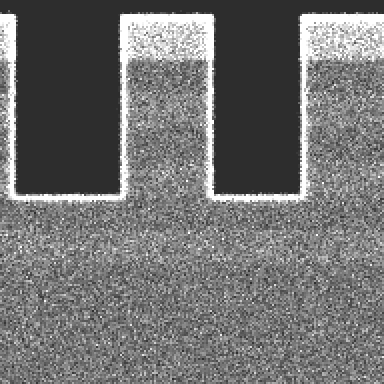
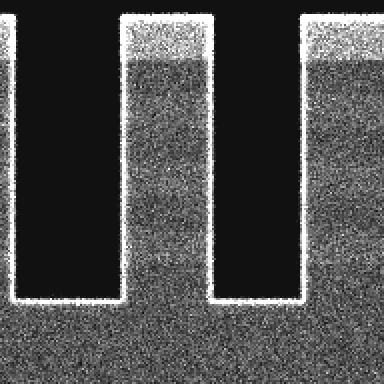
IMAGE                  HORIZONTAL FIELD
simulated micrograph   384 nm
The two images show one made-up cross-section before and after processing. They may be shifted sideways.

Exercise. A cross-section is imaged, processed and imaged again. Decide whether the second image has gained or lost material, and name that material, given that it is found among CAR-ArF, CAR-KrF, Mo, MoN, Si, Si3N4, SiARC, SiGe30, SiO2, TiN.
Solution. removed: Si and SiGe30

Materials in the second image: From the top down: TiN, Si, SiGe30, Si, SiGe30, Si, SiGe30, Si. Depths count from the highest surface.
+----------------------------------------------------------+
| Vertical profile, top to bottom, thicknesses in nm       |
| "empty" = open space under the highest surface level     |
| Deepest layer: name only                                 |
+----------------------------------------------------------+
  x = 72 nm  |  empty 284, Si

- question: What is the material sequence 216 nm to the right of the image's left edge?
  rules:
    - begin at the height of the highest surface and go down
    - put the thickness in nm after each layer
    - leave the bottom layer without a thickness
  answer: empty 284, Si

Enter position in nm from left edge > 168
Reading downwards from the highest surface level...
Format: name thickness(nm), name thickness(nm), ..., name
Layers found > TiN 44, Si 34, SiGe30 34, Si 34, SiGe30 34, Si 34, SiGe30 34, Si